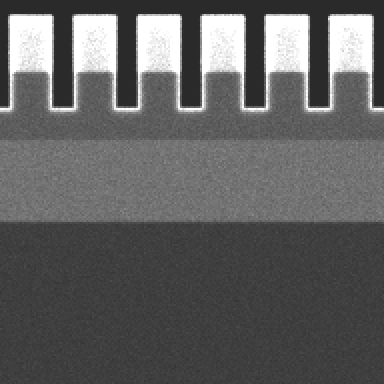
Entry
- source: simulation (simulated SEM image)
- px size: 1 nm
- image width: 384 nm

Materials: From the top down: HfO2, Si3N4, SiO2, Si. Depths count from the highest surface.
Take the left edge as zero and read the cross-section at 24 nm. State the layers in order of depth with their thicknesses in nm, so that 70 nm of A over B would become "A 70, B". HfO2 56, Si3N4 68, SiO2 82, Si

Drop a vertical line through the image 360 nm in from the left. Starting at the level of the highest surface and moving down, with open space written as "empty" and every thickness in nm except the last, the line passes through HfO2 56, Si3N4 68, SiO2 82, Si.